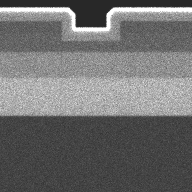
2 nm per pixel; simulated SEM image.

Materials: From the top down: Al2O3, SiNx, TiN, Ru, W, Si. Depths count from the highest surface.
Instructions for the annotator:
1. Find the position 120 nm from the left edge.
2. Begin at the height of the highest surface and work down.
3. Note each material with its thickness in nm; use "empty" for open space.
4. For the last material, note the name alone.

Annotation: Al2O3 26, SiNx 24, TiN 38, Ru 52, W 76, Si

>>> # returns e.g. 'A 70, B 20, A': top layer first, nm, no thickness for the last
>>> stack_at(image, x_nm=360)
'Al2O3 26, SiNx 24, TiN 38, Ru 52, W 76, Si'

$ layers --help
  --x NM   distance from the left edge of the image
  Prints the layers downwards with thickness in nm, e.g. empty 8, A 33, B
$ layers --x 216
empty 10, Al2O3 56, TiN 22, Ru 52, W 76, Si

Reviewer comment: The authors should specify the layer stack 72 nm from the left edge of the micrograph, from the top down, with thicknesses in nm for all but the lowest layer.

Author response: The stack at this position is Al2O3 26, SiNx 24, TiN 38, Ru 52, W 76, Si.